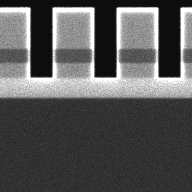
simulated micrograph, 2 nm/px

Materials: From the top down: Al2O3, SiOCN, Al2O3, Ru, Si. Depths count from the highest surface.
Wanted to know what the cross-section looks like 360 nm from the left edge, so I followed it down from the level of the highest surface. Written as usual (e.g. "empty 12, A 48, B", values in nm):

empty 140, Ru 40, Si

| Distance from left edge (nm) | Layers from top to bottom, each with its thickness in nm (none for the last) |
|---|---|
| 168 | Al2O3 82, SiOCN 28, Al2O3 30, Ru 40, Si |